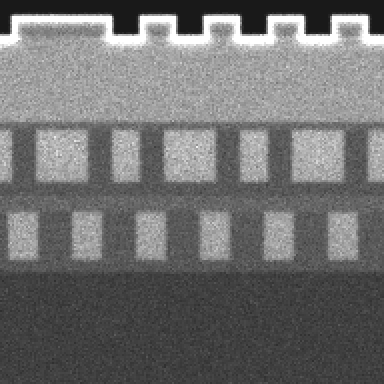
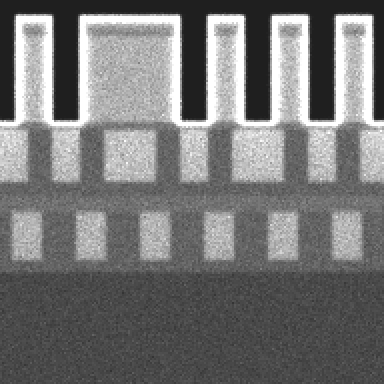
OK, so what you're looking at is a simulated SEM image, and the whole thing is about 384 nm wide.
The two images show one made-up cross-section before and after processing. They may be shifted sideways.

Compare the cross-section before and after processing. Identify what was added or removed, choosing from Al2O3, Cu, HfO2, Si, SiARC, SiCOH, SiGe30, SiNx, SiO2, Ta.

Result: SiO2 removed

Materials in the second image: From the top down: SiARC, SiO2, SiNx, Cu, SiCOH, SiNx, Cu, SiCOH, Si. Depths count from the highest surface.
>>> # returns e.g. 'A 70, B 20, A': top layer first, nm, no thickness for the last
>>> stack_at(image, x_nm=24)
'SiARC 20, SiO2 86, SiNx 8, Cu 52, SiCOH 14, SiNx 16, Cu 48, SiCOH 12, Si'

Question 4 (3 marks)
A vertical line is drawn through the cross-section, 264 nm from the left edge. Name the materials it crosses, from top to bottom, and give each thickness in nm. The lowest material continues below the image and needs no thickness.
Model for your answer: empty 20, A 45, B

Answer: empty 106, SiNx 8, Cu 52, SiCOH 14, SiNx 16, SiCOH 60, Si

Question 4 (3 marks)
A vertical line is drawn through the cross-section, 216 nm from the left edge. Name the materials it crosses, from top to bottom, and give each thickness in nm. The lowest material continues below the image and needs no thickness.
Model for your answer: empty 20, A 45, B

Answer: SiARC 20, SiO2 86, SiNx 8, SiCOH 66, SiNx 16, Cu 48, SiCOH 12, Si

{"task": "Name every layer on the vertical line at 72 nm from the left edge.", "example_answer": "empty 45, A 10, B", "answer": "empty 106, SiNx 8, Cu 52, SiCOH 14, SiNx 16, SiCOH 60, Si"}